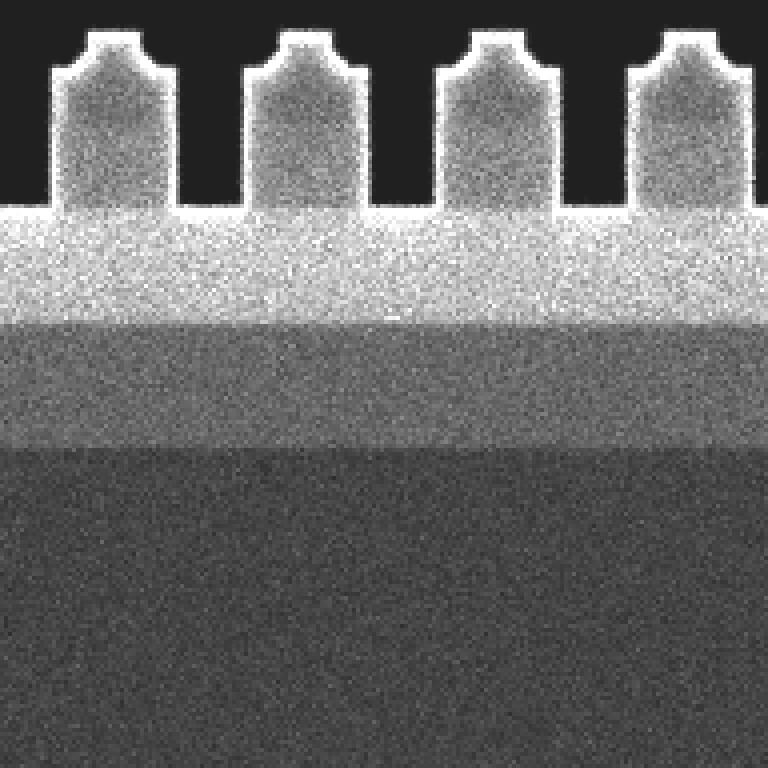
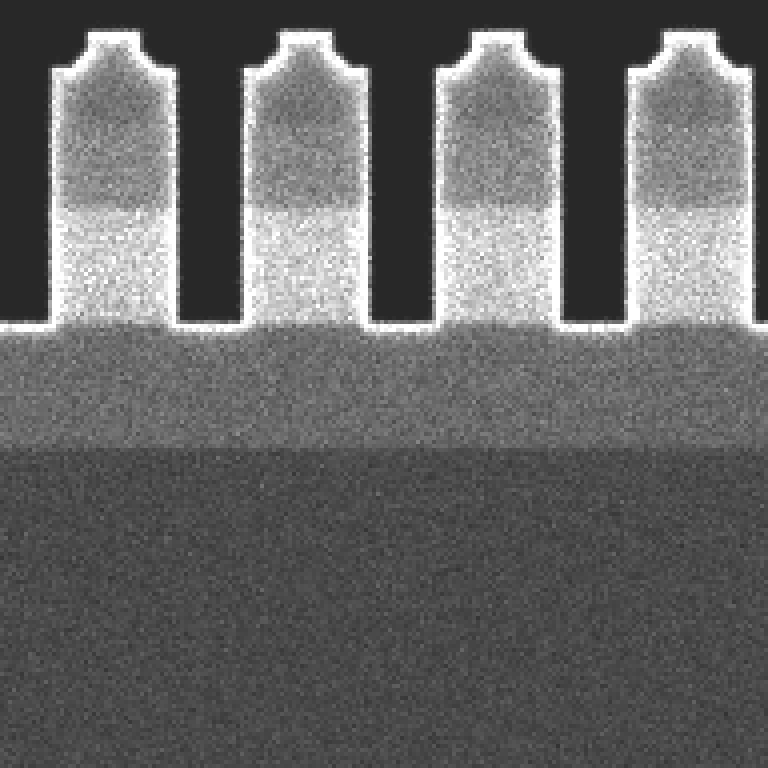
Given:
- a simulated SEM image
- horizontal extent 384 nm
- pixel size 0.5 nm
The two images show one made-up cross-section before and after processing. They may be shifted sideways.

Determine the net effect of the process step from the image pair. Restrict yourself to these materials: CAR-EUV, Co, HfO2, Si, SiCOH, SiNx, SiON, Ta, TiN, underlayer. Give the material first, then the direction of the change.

Co: removed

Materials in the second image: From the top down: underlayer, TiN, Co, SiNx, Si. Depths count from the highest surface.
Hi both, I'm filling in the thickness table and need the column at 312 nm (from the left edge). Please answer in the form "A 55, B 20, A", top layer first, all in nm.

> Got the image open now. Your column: empty 146, SiNx 62, Si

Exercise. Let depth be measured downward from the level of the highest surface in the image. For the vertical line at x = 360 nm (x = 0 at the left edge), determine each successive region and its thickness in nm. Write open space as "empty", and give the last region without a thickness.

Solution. empty 12, underlayer 34, TiN 42, Co 58, SiNx 62, Si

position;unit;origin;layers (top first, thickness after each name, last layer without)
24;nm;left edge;empty 146, SiNx 62, Si